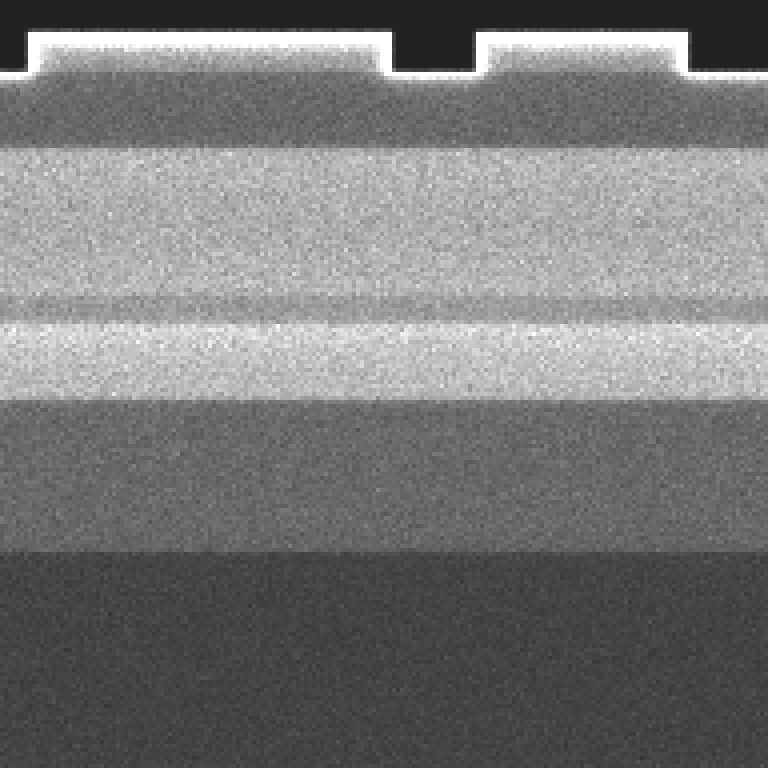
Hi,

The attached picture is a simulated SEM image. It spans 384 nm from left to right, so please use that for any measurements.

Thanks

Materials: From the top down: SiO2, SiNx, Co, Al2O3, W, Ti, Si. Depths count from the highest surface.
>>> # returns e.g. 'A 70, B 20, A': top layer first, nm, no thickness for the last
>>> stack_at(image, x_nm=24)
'SiO2 20, SiNx 38, Co 74, Al2O3 14, W 38, Ti 76, Si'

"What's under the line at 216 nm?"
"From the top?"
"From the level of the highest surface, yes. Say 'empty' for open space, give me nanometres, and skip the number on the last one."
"empty 20, SiNx 38, Co 74, Al2O3 14, W 38, Ti 76, Si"